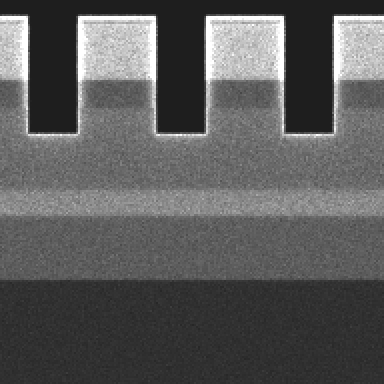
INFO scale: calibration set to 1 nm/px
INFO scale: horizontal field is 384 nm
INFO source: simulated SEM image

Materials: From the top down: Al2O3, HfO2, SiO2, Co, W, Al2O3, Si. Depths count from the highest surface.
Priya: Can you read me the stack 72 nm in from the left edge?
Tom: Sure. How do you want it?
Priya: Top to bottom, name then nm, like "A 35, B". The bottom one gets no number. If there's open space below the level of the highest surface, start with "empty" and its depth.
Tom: empty 118, Co 56, W 26, Al2O3 64, Si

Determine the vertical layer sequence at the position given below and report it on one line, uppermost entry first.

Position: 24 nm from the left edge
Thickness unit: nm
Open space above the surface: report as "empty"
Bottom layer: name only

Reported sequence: Al2O3 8, HfO2 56, SiO2 28, Co 82, W 26, Al2O3 64, Si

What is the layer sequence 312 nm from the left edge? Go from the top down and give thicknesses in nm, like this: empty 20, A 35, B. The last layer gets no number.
empty 118, Co 56, W 26, Al2O3 64, Si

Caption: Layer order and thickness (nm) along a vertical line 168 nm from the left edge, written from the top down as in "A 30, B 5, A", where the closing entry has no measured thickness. empty 118, Co 56, W 26, Al2O3 64, Si